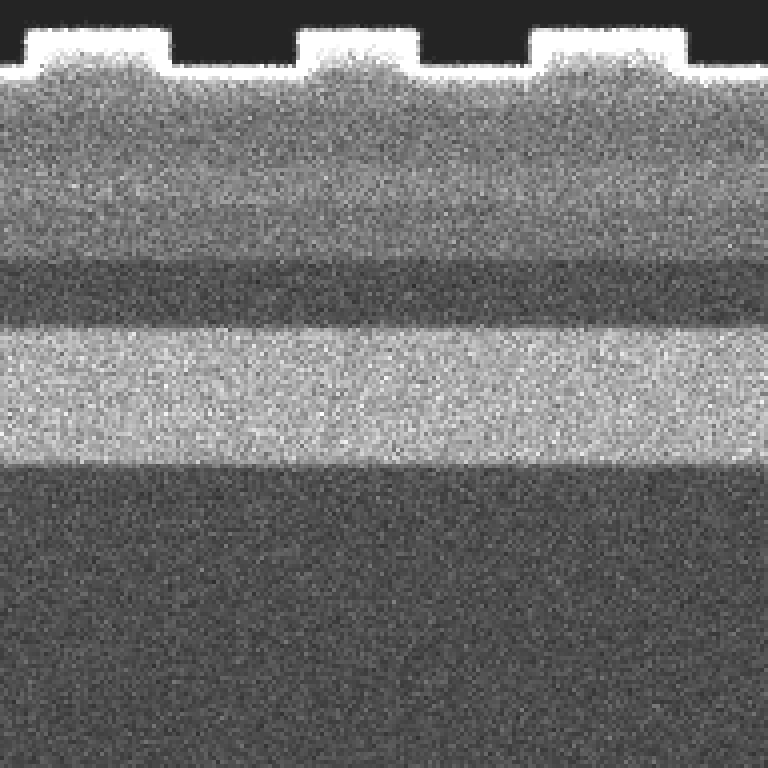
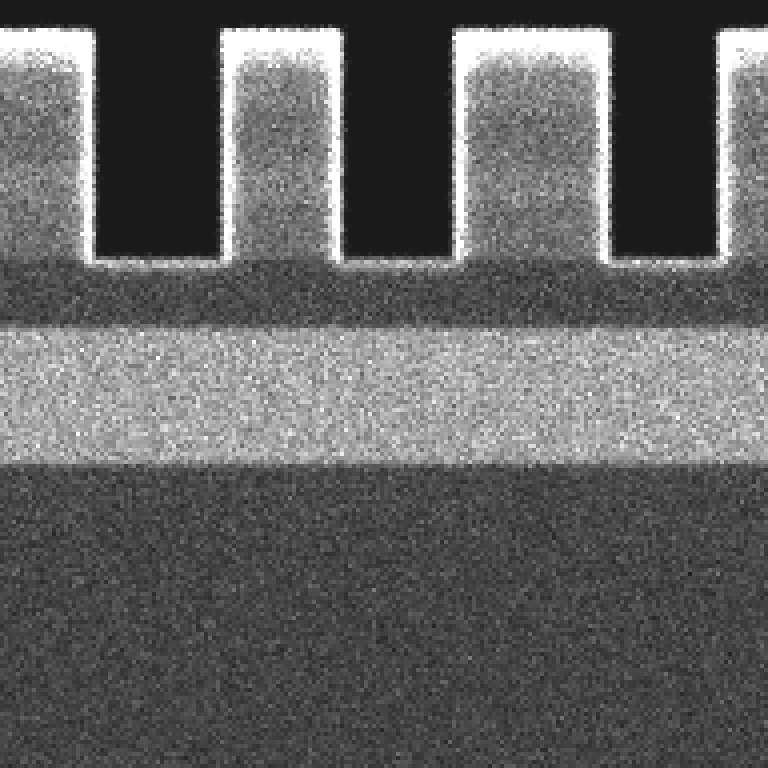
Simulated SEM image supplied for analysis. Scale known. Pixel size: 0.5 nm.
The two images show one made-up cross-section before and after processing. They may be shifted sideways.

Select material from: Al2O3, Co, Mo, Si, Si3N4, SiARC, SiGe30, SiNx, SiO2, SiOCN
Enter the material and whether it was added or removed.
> Si3N4 and SiNx / removed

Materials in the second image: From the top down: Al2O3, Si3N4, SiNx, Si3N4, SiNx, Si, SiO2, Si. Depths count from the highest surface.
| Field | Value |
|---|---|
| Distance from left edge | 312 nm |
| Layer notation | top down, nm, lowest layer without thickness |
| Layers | empty 114, Si 34, SiO2 68, Si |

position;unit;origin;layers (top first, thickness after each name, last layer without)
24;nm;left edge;Al2O3 18, Si3N4 20, SiNx 28, Si3N4 20, SiNx 28, Si 34, SiO2 68, Si